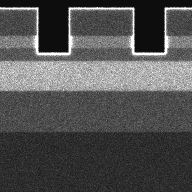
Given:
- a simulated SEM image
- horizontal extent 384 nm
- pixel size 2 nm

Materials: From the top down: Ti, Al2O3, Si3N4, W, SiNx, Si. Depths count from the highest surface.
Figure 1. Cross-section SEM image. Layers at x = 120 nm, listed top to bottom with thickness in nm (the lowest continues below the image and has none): empty 90, Si3N4 16, W 60, SiNx 82, Si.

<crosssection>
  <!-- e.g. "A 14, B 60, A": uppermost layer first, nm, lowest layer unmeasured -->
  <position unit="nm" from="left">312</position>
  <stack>empty 90, Si3N4 16, W 60, SiNx 82, Si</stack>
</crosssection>